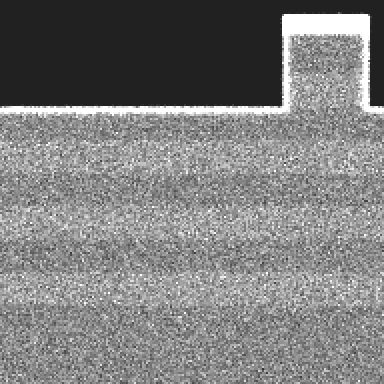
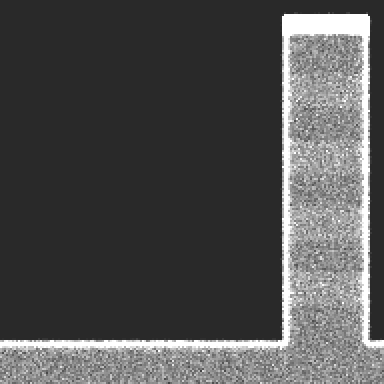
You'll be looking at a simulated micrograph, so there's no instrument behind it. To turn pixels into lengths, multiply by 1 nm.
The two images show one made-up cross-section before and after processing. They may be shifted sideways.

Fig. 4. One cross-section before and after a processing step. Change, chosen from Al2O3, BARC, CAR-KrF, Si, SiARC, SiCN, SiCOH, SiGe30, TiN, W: Si and SiGe30 removed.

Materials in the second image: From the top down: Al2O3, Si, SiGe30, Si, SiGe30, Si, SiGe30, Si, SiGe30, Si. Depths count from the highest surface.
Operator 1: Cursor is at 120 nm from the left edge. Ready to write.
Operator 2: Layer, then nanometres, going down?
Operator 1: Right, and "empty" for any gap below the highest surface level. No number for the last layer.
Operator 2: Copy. empty 326, Si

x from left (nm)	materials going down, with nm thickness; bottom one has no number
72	empty 326, Si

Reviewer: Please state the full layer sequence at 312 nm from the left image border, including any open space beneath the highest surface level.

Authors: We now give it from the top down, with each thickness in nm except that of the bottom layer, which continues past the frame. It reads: Al2O3 18, Si 40, SiGe30 34, Si 32, SiGe30 34, Si 32, SiGe30 34, Si 32, SiGe30 34, Si